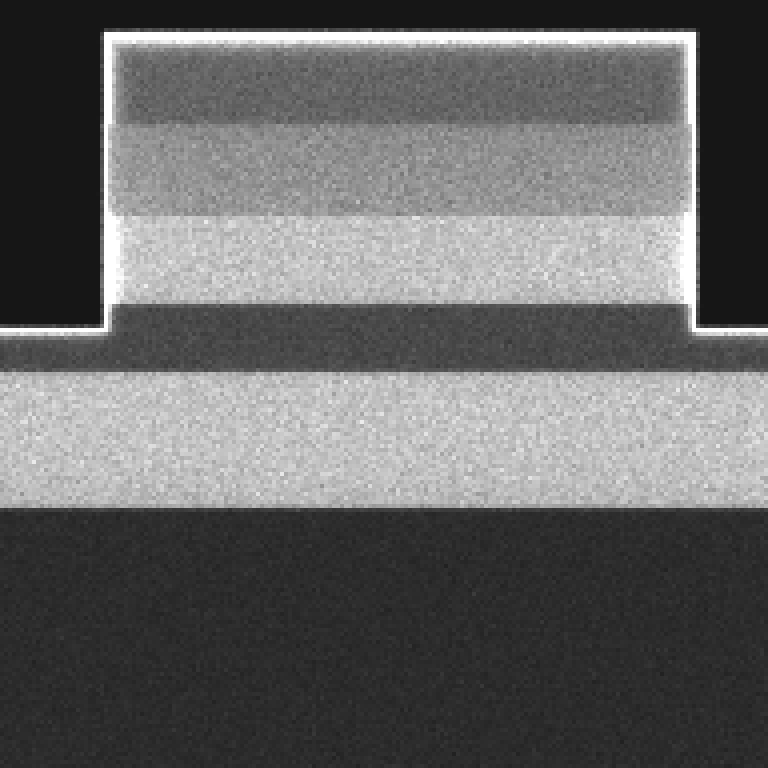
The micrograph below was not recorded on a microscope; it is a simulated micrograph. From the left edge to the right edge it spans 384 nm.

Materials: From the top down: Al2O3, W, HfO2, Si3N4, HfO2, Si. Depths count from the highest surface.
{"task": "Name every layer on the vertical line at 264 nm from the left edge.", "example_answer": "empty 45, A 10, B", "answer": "Al2O3 46, W 46, HfO2 44, Si3N4 34, HfO2 68, Si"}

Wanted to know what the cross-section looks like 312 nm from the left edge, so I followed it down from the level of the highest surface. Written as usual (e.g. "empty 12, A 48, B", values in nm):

Al2O3 46, W 46, HfO2 44, Si3N4 34, HfO2 68, Si